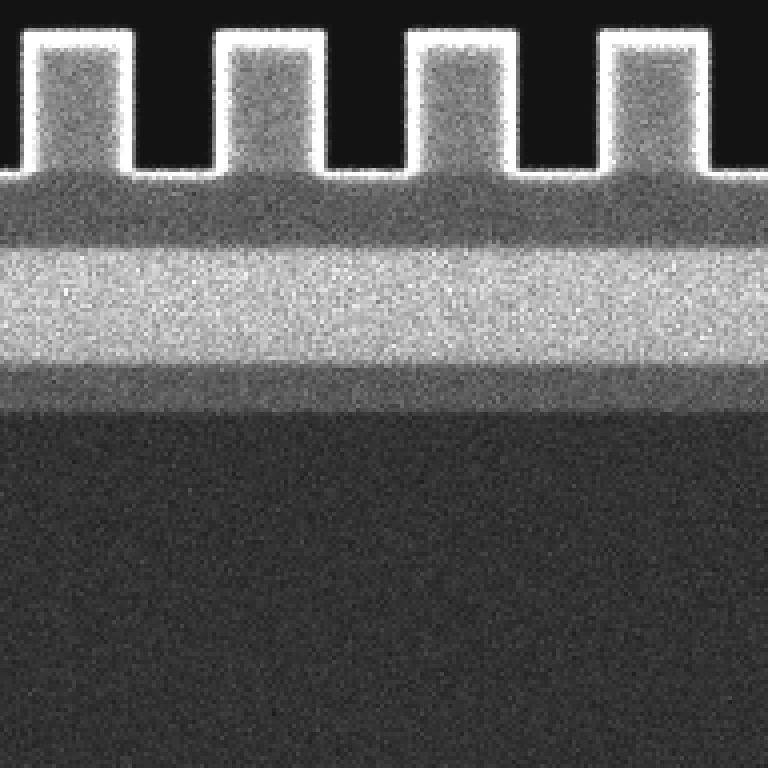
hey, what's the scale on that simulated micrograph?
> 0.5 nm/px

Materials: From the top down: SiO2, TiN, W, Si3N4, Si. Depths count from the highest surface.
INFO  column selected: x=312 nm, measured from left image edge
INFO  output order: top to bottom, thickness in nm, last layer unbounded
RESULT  SiO2 70, TiN 38, W 58, Si3N4 24, Si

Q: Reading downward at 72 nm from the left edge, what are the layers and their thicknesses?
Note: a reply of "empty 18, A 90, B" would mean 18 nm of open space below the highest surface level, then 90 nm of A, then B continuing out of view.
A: empty 70, TiN 38, W 58, Si3N4 24, Si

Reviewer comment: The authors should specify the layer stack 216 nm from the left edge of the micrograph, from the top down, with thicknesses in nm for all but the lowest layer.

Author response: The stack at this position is SiO2 70, TiN 38, W 58, Si3N4 24, Si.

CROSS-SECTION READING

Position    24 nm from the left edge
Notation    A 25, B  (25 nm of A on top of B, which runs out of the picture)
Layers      SiO2 70, TiN 38, W 58, Si3N4 24, Si